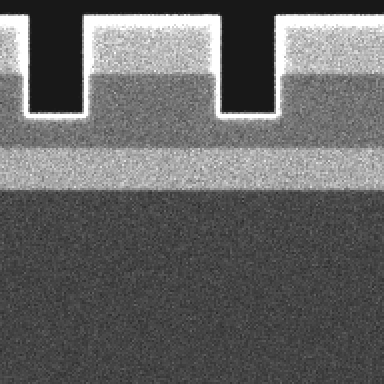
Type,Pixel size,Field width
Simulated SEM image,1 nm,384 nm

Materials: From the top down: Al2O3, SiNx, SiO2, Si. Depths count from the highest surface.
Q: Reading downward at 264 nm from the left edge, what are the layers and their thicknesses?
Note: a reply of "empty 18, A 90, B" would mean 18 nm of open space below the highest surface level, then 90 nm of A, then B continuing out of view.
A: empty 98, SiNx 34, SiO2 42, Si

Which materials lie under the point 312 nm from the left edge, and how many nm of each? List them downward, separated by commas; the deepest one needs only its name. Al2O3 58, SiNx 74, SiO2 42, Si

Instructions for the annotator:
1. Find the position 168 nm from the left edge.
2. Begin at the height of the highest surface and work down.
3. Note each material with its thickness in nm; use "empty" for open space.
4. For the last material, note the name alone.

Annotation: Al2O3 58, SiNx 74, SiO2 42, Si